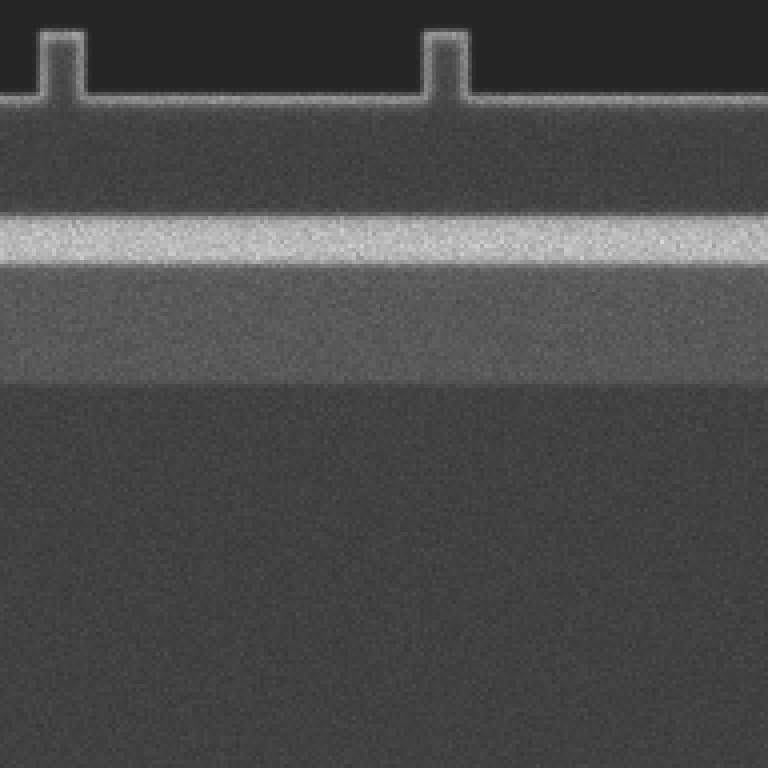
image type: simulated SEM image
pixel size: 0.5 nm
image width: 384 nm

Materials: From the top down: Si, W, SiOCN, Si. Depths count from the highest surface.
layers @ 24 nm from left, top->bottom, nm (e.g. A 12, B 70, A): Si 92, W 24, SiOCN 60, Si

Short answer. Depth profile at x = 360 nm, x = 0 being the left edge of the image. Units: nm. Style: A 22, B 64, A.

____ empty 32, Si 60, W 24, SiOCN 60, Si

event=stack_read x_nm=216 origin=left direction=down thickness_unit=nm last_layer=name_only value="Si 92, W 24, SiOCN 60, Si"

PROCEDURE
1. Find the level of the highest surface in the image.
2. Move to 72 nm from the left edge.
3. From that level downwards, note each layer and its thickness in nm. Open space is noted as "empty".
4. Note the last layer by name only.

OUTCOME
empty 32, Si 60, W 24, SiOCN 60, Si